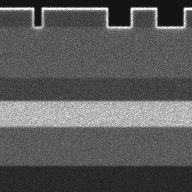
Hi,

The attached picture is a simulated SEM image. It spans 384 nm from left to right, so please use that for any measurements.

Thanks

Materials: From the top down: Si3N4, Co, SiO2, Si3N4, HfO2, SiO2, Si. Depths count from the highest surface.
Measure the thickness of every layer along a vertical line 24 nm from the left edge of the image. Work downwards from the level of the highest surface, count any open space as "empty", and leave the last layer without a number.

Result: Si3N4 38, Co 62, SiO2 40, Si3N4 46, HfO2 52, SiO2 78, Si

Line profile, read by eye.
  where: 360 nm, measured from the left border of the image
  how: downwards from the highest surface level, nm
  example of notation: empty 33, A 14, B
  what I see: empty 38, Co 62, SiO2 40, Si3N4 46, HfO2 52, SiO2 78, Si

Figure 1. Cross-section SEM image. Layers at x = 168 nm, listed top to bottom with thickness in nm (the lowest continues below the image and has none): Si3N4 38, Co 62, SiO2 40, Si3N4 46, HfO2 52, SiO2 78, Si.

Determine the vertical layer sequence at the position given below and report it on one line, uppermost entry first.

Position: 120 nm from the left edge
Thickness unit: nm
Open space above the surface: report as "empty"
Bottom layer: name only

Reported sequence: Si3N4 38, Co 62, SiO2 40, Si3N4 46, HfO2 52, SiO2 78, Si